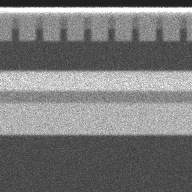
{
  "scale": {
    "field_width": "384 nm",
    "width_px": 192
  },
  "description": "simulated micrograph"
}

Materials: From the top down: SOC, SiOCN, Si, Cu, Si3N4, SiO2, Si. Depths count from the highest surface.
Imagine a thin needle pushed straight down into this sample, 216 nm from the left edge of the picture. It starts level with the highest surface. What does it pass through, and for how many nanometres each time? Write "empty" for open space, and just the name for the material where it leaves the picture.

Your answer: SOC 18, SiOCN 24, Si 84, Cu 40, Si3N4 24, SiO2 64, Si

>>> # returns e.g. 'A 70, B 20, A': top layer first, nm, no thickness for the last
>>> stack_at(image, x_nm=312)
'SOC 18, SiOCN 24, Si 84, Cu 40, Si3N4 24, SiO2 64, Si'